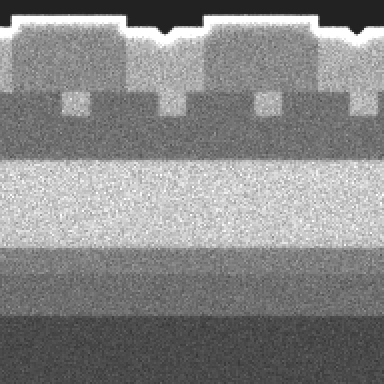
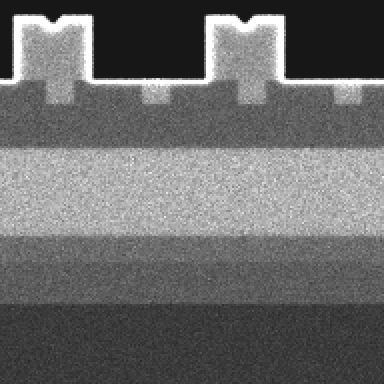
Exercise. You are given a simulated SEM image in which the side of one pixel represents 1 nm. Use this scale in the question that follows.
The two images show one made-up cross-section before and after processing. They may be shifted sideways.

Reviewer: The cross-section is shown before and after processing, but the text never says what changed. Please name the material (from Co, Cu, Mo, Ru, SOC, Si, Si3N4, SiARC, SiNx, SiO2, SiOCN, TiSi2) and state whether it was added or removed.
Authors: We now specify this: SOC, removed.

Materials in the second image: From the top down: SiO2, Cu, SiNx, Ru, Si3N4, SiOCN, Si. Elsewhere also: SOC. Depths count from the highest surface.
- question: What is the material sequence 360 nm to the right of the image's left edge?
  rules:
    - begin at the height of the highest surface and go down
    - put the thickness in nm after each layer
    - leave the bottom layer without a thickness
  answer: empty 64, Cu 24, SiNx 44, Ru 88, Si3N4 26, SiOCN 42, Si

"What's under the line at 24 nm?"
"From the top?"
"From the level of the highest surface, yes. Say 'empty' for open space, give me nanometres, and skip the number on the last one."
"SiO2 64, SiNx 68, Ru 88, Si3N4 26, SiOCN 42, Si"